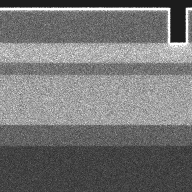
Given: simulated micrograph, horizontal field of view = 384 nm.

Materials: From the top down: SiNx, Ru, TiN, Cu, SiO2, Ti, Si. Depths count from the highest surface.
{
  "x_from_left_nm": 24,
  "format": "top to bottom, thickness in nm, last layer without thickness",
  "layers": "SiNx 70, Ru 40, TiN 24, Cu 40, SiO2 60, Ti 42, Si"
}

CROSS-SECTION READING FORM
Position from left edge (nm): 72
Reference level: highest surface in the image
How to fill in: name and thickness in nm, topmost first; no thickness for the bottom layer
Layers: SiNx 70, Ru 40, TiN 24, Cu 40, SiO2 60, Ti 42, Si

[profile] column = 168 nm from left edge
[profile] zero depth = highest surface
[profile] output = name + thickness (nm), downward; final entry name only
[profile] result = SiNx 70, Ru 40, TiN 24, Cu 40, SiO2 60, Ti 42, Si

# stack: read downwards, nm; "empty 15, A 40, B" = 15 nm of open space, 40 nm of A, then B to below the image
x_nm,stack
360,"empty 70, Ru 40, TiN 24, Cu 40, SiO2 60, Ti 42, Si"